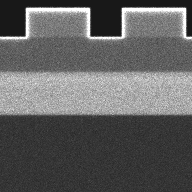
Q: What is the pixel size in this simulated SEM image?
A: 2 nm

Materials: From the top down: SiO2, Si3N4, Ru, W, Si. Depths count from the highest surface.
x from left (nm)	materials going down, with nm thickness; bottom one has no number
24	empty 58, Si3N4 70, Ru 10, W 76, Si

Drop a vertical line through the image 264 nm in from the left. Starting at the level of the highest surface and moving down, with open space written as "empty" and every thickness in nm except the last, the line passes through SiO2 58, Si3N4 70, Ru 10, W 76, Si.